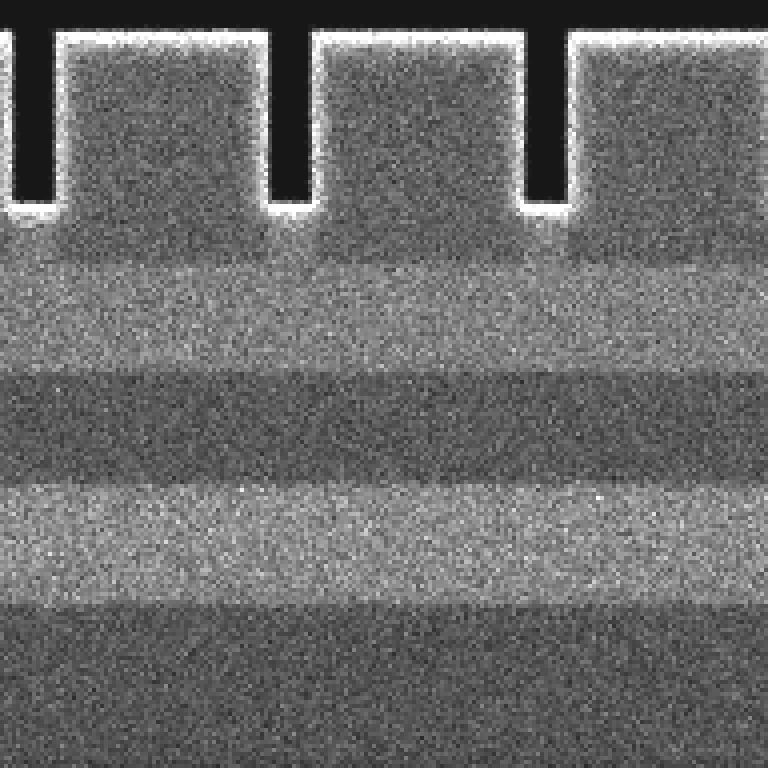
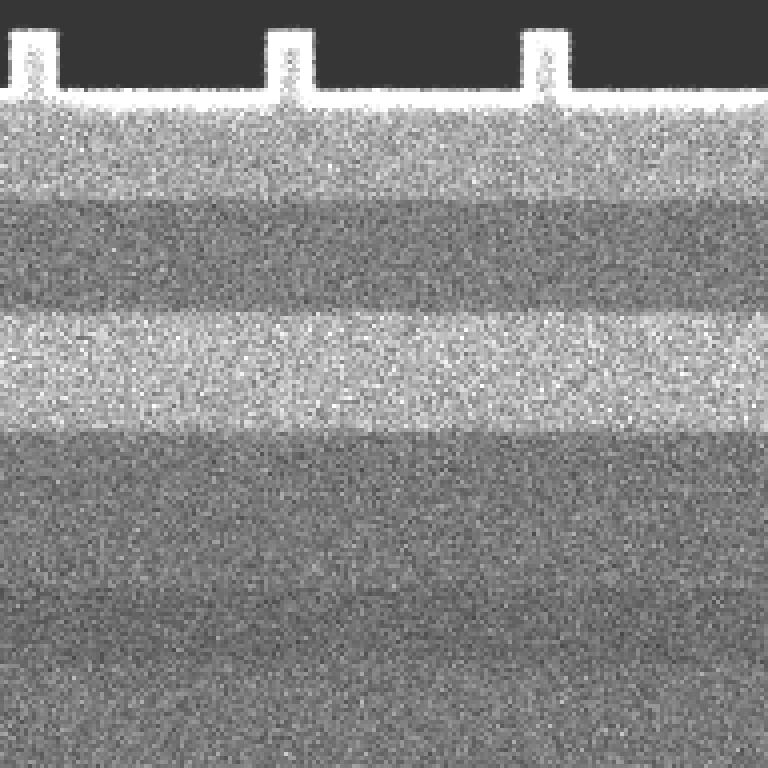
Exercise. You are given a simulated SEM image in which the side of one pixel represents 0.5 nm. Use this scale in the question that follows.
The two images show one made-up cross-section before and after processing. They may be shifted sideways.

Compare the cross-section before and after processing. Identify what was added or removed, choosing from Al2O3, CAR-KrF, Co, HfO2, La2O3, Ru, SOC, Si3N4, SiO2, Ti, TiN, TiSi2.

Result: SOC removed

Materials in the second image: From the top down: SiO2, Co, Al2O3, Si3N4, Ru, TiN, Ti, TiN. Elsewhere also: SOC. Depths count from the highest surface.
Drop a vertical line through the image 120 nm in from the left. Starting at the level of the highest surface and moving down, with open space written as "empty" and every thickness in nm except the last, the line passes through empty 30, Al2O3 54, Si3N4 56, Ru 60, TiN 78, Ti 38, TiN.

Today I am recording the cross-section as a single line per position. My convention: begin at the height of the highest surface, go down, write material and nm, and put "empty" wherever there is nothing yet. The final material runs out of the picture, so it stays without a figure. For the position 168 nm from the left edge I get empty 30, Al2O3 54, Si3N4 56, Ru 60, TiN 78, Ti 38, TiN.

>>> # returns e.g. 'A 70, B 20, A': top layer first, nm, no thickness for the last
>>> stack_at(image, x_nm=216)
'empty 30, Al2O3 54, Si3N4 56, Ru 60, TiN 78, Ti 38, TiN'